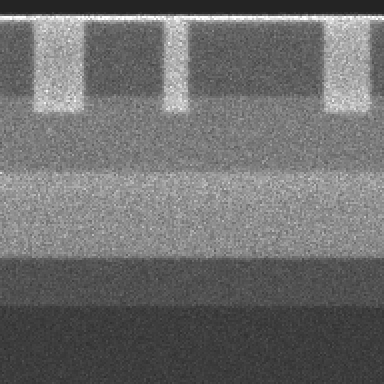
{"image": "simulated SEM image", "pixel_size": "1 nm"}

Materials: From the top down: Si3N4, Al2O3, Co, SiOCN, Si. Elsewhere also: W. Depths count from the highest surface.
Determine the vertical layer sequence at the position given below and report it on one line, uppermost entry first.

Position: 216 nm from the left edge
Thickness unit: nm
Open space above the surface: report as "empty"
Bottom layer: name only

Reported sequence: Si3N4 80, Al2O3 76, Co 86, SiOCN 48, Si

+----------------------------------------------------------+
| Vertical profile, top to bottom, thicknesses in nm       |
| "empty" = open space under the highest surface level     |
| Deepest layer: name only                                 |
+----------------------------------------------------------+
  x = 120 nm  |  Si3N4 80, Al2O3 76, Co 86, SiOCN 48, Si